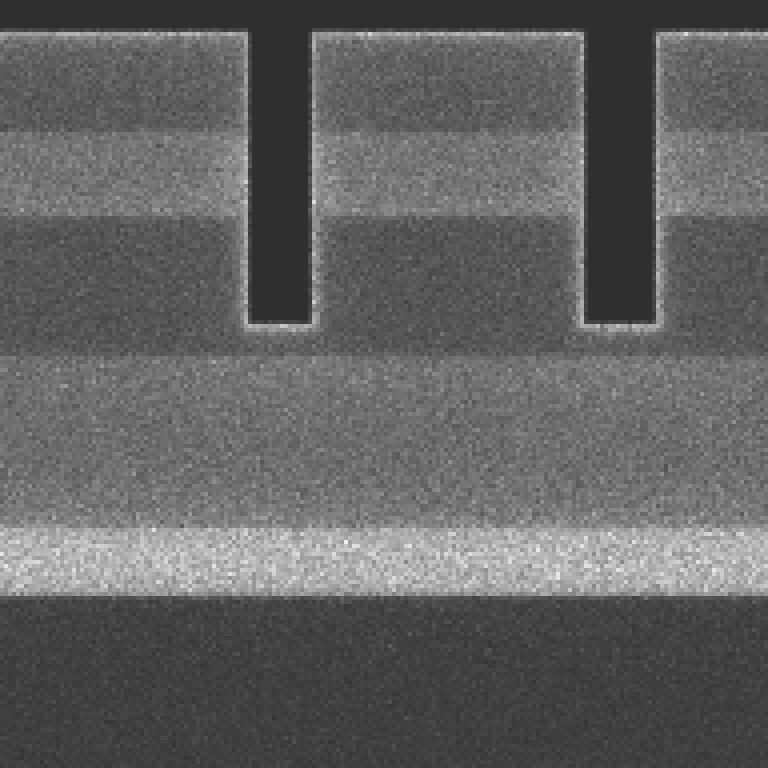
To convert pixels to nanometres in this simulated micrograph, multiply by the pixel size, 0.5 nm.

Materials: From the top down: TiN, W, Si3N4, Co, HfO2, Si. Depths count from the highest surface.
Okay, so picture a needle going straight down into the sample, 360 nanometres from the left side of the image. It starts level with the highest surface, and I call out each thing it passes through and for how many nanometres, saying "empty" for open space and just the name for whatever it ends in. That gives TiN 50, W 42, Si3N4 70, Co 86, HfO2 34, Si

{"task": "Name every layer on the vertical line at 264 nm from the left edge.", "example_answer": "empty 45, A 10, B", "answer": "TiN 50, W 42, Si3N4 70, Co 86, HfO2 34, Si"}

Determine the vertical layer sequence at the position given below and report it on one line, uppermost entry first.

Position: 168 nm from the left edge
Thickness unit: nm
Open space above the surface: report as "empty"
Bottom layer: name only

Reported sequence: TiN 50, W 42, Si3N4 70, Co 86, HfO2 34, Si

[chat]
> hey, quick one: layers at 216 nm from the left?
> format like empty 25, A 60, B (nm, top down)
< TiN 50, W 42, Si3N4 70, Co 86, HfO2 34, Si